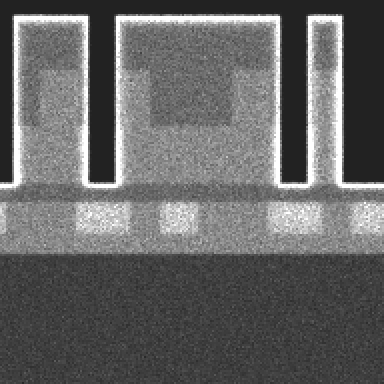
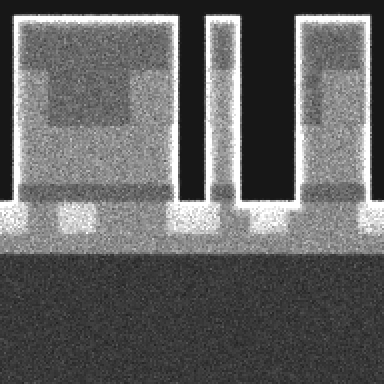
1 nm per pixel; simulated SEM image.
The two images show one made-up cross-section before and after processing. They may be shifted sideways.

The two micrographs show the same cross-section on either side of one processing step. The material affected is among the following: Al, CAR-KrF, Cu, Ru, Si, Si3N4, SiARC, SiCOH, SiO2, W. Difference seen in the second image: Si3N4 removed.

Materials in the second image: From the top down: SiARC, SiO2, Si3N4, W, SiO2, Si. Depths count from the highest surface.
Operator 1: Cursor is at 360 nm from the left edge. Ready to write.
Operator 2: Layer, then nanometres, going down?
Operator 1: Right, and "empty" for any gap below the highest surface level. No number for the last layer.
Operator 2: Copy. SiARC 110, SiO2 58, Si3N4 18, W 32, SiO2 20, Si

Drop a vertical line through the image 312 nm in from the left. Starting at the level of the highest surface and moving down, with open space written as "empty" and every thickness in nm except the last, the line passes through SiARC 110, SiO2 58, Si3N4 18, SiO2 52, Si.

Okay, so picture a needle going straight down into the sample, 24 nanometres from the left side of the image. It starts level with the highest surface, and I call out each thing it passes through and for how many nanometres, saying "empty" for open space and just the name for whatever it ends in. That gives SiARC 54, SiO2 114, Si3N4 18, W 32, SiO2 20, Si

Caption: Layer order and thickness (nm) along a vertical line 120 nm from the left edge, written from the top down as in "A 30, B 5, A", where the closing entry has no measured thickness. SiARC 110, SiO2 58, Si3N4 18, SiO2 52, Si